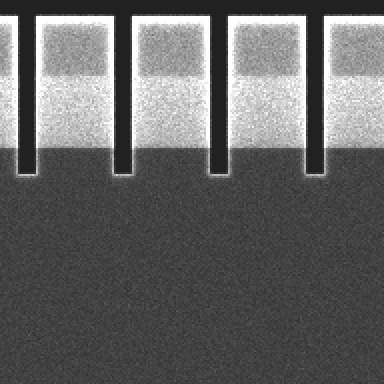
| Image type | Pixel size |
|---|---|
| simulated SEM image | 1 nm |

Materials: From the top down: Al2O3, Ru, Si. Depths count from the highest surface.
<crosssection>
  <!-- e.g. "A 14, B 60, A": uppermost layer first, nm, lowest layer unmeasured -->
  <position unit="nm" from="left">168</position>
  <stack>Al2O3 60, Ru 72, Si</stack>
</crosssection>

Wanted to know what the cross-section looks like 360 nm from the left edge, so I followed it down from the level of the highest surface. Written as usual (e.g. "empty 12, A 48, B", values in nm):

Al2O3 60, Ru 72, Si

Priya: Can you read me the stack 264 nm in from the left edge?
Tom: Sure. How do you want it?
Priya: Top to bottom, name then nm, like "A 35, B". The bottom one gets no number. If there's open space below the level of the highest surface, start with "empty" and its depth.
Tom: Al2O3 60, Ru 72, Si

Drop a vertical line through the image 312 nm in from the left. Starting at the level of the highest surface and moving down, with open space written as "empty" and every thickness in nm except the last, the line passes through empty 158, Si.